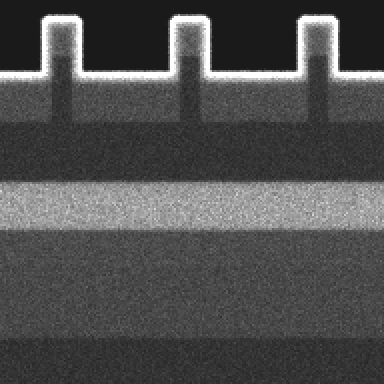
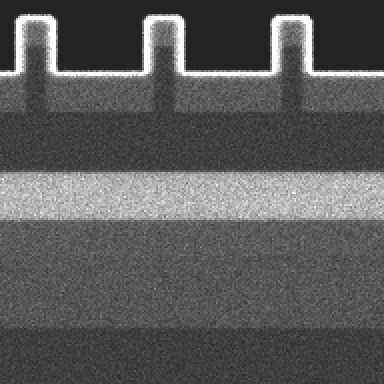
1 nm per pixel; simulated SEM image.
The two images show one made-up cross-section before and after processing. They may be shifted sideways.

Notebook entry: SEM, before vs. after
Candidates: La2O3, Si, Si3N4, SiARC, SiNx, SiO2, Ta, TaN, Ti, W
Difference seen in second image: SiO2 removed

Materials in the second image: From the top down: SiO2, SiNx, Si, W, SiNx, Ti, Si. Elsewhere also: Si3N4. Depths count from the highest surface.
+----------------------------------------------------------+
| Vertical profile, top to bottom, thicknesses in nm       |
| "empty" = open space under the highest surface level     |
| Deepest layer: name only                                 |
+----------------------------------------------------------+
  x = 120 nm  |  empty 56, SiNx 40, Si 60, W 48, SiNx 36, Ti 72, Si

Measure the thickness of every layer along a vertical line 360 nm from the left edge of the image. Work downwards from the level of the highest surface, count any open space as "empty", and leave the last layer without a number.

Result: empty 56, SiNx 40, Si 60, W 48, SiNx 36, Ti 72, Si